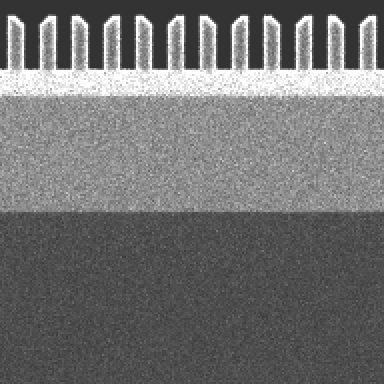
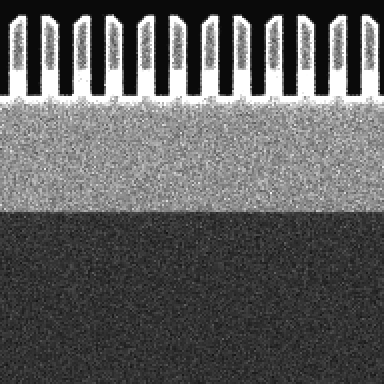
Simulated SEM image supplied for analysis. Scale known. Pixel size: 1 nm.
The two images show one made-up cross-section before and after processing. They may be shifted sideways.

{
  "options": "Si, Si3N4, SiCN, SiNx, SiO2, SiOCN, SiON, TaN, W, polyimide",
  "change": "removed",
  "material": "W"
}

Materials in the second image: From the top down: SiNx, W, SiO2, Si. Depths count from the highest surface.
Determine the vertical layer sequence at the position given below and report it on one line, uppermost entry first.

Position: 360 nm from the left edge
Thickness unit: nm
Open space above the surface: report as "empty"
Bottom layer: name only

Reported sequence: empty 80, SiO2 116, Si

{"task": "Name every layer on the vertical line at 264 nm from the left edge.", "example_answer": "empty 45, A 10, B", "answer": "empty 80, SiO2 116, Si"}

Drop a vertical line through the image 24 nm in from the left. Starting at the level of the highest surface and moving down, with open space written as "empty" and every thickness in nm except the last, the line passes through SiNx 54, W 26, SiO2 116, Si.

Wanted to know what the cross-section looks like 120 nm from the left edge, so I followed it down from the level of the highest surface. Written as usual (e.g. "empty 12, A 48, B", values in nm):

empty 8, SiNx 46, W 26, SiO2 116, Si